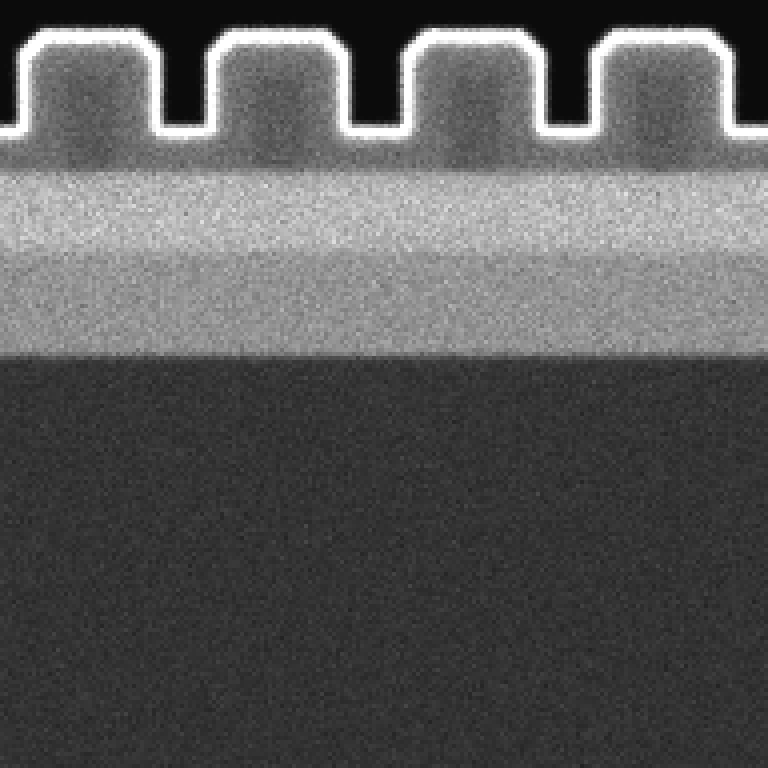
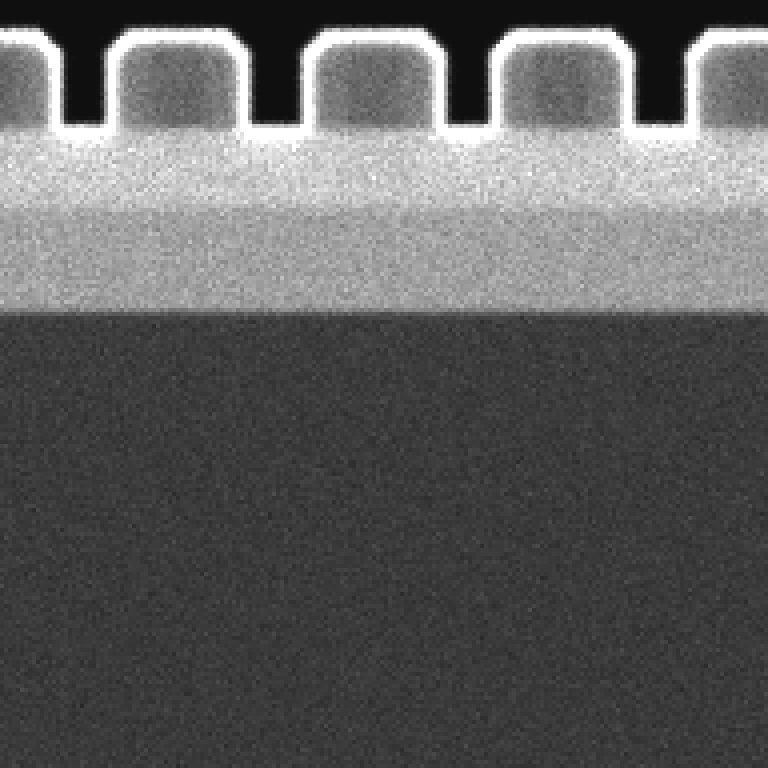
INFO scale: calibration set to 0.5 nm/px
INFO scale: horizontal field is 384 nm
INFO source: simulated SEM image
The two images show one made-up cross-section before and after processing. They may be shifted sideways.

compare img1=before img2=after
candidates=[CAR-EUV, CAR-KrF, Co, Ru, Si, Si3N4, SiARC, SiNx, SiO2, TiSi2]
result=removed:Si3N4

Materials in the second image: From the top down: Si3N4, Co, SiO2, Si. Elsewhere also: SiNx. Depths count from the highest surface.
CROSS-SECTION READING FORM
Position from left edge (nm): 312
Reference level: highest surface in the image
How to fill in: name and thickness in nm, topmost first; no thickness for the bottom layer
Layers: empty 8, Si3N4 40, Co 40, SiO2 52, Si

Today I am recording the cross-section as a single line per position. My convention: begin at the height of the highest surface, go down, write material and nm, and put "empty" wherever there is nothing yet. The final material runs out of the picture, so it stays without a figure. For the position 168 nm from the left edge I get Si3N4 48, Co 40, SiO2 52, Si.